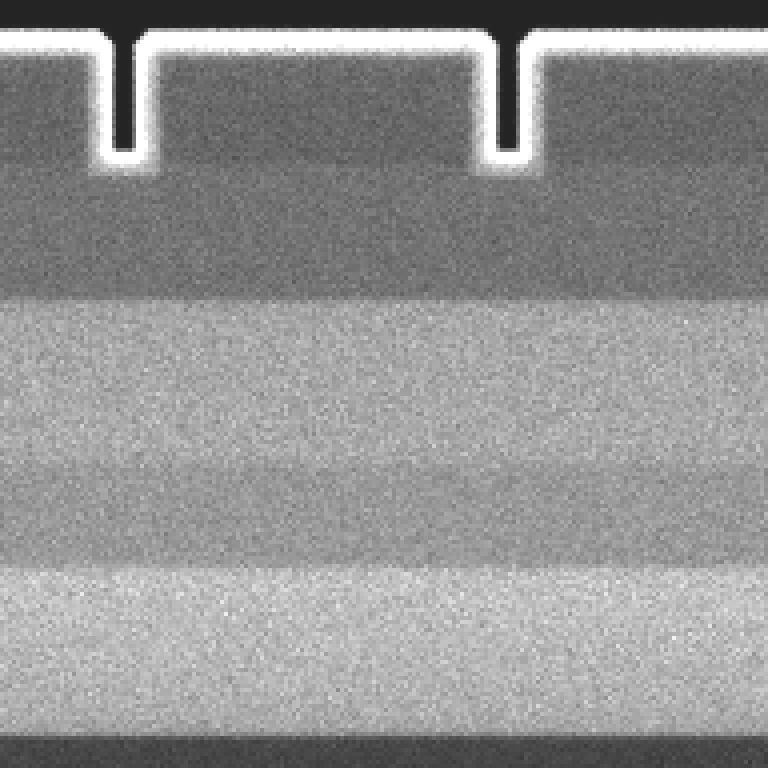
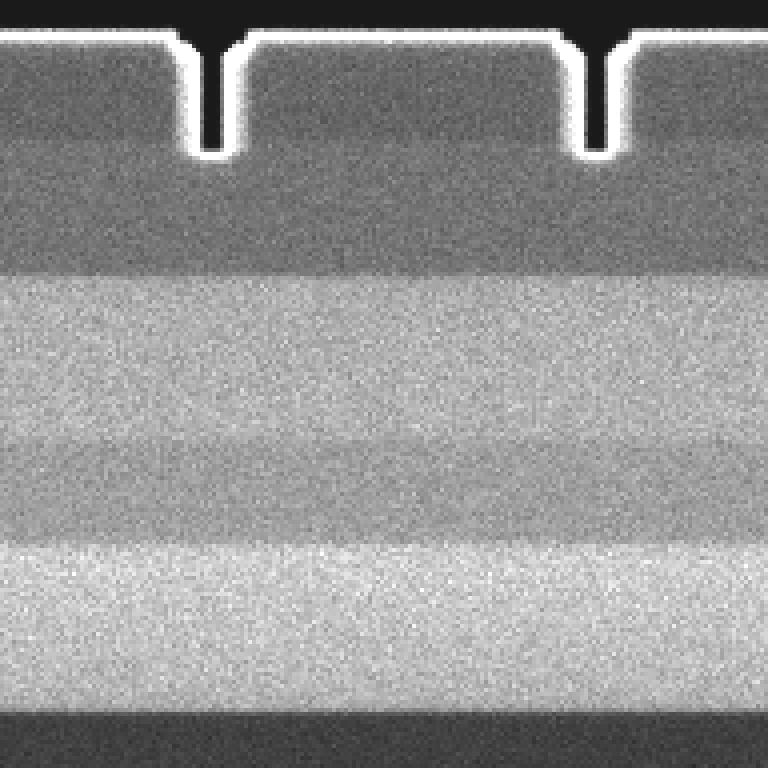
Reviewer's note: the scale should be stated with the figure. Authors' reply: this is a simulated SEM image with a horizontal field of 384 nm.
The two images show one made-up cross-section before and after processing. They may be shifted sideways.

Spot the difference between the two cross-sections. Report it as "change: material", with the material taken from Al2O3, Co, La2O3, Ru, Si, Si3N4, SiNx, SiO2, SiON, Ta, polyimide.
removed: Al2O3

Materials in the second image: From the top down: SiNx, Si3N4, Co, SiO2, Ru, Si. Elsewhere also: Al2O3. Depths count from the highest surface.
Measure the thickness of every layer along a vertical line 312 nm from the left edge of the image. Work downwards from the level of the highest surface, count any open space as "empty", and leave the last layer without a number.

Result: empty 6, Al2O3 54, Si3N4 62, Co 82, SiO2 52, Ru 84, Si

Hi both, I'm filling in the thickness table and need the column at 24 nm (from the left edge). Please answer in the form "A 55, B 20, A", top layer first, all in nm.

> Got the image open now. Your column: SiNx 54, Si3N4 68, Co 82, SiO2 52, Ru 84, Si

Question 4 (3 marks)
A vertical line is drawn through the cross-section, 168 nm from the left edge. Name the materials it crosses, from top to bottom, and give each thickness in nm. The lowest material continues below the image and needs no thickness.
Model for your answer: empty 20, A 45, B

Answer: SiNx 54, Si3N4 68, Co 82, SiO2 52, Ru 84, Si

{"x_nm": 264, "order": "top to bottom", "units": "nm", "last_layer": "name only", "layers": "SiNx 54, Si3N4 68, Co 82, SiO2 52, Ru 84, Si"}